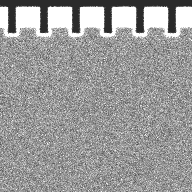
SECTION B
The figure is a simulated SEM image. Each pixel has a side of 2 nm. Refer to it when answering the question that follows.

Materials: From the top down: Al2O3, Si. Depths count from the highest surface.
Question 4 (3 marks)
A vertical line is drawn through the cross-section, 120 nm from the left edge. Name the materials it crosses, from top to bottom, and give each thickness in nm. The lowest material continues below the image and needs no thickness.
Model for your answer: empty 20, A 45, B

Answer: Al2O3 38, Si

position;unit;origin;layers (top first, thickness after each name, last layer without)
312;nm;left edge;Al2O3 38, Si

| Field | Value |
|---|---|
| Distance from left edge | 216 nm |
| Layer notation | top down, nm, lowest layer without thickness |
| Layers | empty 52, Si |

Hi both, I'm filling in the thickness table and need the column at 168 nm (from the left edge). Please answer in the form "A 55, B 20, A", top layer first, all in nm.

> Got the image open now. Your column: Al2O3 38, Si